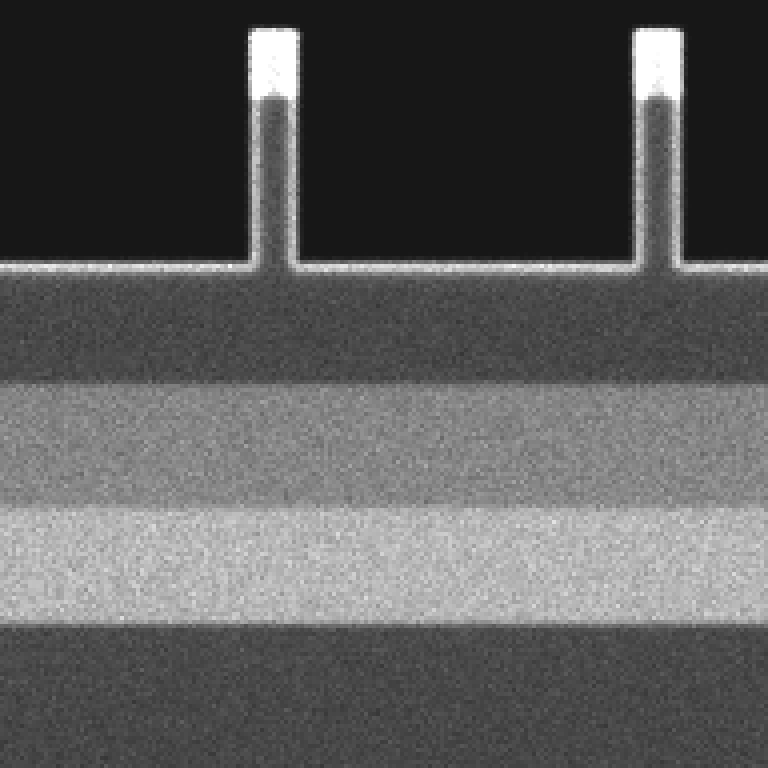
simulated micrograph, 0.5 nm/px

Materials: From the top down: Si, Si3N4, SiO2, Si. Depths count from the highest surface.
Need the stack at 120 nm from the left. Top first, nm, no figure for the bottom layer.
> empty 116, Si 60, Si3N4 62, SiO2 58, Si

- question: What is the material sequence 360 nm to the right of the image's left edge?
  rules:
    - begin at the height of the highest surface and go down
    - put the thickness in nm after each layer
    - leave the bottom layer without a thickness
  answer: empty 116, Si 60, Si3N4 62, SiO2 58, Si